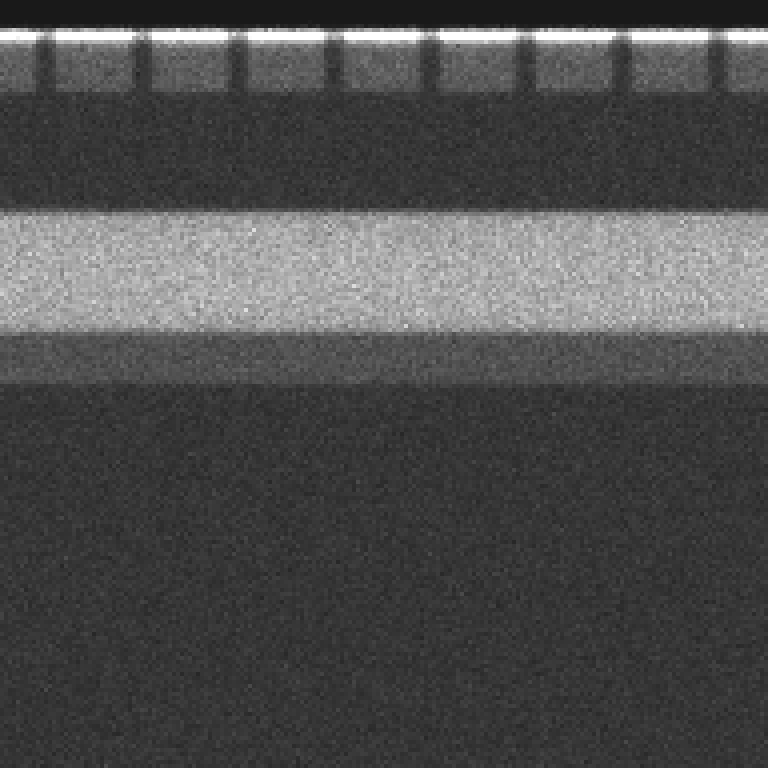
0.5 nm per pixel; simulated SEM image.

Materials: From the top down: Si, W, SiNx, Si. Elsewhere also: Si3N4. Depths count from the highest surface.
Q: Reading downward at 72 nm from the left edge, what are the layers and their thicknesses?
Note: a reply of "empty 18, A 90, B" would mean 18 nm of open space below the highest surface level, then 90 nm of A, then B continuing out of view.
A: Si 90, W 60, SiNx 26, Si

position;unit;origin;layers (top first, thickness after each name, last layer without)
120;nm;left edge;Si 90, W 60, SiNx 26, Si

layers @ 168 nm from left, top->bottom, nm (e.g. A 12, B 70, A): Si 90, W 60, SiNx 26, Si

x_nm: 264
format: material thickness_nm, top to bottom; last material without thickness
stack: Si 90, W 60, SiNx 26, Si